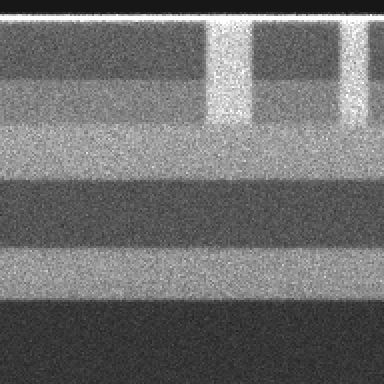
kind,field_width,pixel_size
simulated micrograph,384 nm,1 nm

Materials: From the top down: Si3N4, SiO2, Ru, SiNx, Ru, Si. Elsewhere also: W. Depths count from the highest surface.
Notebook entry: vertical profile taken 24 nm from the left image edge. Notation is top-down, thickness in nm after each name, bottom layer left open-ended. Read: Si3N4 64, SiO2 44, Ru 56, SiNx 68, Ru 52, Si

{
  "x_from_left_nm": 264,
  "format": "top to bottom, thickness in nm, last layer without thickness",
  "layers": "Si3N4 64, SiO2 44, Ru 56, SiNx 68, Ru 52, Si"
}